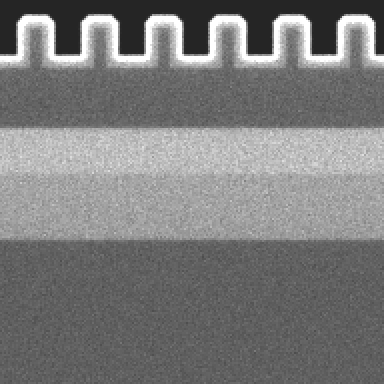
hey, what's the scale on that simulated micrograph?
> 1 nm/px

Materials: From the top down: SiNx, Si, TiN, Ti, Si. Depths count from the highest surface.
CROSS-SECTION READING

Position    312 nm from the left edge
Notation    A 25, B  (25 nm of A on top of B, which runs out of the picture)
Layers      empty 40, SiNx 12, Si 60, TiN 46, Ti 66, Si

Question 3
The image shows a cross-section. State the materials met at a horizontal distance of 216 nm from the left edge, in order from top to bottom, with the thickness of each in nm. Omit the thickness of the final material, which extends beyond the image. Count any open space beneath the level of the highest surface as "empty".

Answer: SiNx 52, Si 60, TiN 46, Ti 66, Si